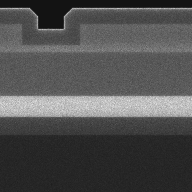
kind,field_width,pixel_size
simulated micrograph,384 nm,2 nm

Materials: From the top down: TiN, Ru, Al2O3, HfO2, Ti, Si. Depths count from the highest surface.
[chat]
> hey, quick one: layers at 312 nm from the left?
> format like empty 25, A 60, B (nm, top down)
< TiN 32, Ru 56, Al2O3 88, HfO2 42, Ti 36, Si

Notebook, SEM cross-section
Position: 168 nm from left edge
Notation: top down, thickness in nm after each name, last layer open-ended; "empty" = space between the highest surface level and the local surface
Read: TiN 32, Ru 56, Al2O3 88, HfO2 42, Ti 36, Si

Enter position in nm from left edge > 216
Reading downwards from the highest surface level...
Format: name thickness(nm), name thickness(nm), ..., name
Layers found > TiN 32, Ru 56, Al2O3 88, HfO2 42, Ti 36, Si